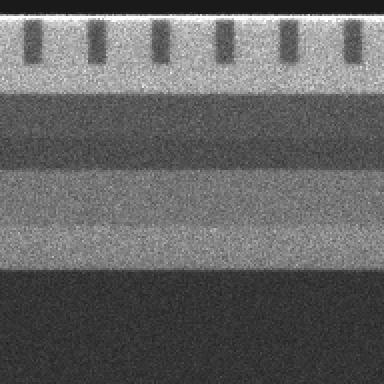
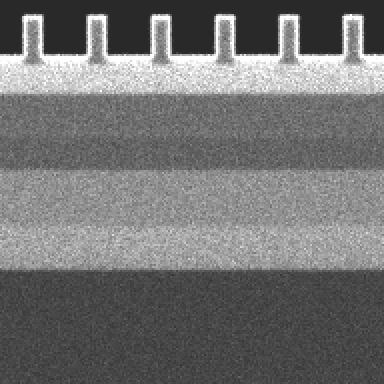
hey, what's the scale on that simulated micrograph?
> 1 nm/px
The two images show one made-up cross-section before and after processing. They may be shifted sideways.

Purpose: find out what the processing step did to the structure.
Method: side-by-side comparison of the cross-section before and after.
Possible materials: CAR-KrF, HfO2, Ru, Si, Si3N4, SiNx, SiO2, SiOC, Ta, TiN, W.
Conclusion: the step removed W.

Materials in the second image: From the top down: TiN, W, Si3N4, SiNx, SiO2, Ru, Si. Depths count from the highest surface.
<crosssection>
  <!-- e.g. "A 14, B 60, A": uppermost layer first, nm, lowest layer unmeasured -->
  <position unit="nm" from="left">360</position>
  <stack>TiN 48, W 30, Si3N4 44, SiNx 32, SiO2 56, Ru 44, Si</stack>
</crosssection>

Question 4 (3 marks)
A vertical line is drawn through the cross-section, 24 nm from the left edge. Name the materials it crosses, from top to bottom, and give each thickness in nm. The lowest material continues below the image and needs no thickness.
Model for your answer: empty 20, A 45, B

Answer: TiN 48, W 30, Si3N4 44, SiNx 32, SiO2 56, Ru 44, Si